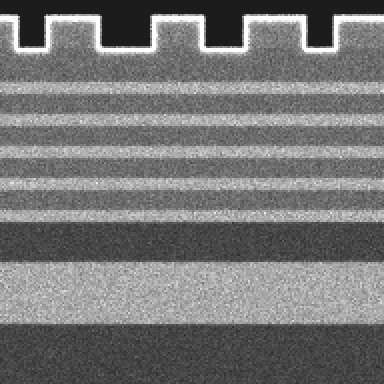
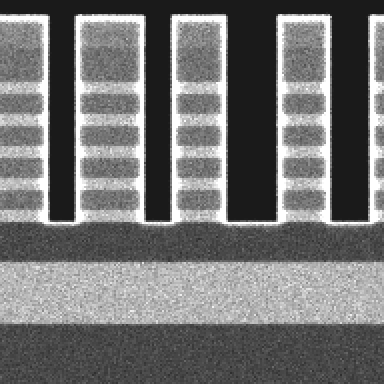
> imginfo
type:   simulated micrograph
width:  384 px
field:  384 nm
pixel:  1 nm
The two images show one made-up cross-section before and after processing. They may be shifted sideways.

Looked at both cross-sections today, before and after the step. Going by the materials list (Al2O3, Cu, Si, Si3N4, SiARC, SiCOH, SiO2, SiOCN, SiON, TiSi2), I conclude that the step removed Al2O3 and SiOCN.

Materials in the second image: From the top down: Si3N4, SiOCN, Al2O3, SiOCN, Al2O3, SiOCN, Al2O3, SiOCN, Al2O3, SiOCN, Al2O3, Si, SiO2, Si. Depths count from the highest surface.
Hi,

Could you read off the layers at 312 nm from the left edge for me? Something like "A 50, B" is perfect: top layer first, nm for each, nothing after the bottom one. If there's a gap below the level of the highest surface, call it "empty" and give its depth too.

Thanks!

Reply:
Si3N4 32, SiOCN 34, Al2O3 12, SiOCN 20, Al2O3 12, SiOCN 20, Al2O3 12, SiOCN 20, Al2O3 12, SiOCN 20, Al2O3 12, Si 40, SiO2 62, Si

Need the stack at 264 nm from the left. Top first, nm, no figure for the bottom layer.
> empty 206, Si 40, SiO2 62, Si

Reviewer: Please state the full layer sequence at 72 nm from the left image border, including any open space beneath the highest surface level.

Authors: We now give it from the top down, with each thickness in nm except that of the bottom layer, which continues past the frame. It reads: empty 206, Si 40, SiO2 62, Si